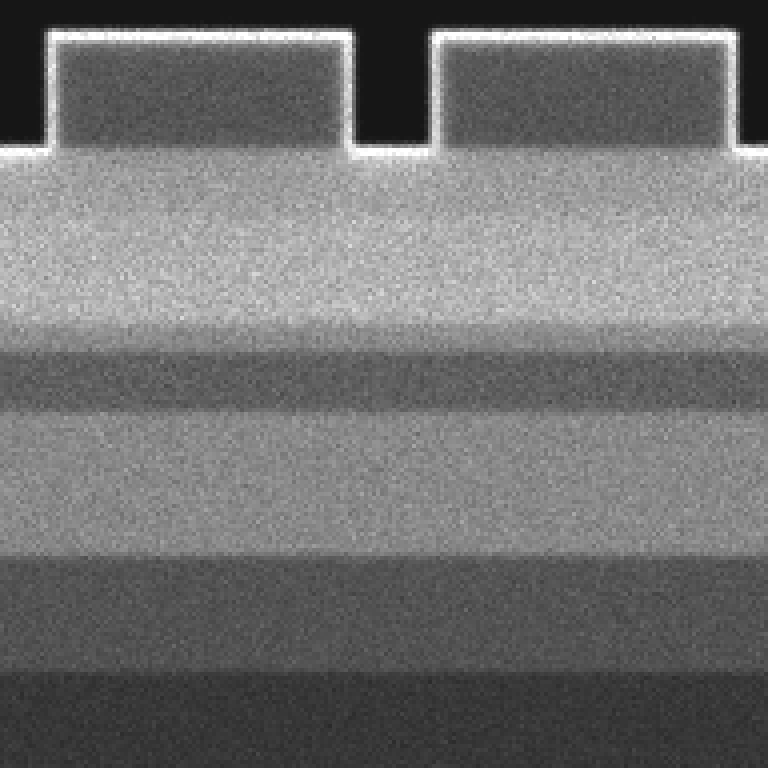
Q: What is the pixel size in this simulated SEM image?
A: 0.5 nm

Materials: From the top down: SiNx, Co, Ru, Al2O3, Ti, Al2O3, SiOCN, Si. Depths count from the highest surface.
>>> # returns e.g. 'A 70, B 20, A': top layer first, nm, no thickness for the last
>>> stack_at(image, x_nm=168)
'SiNx 58, Co 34, Ru 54, Al2O3 14, Ti 30, Al2O3 72, SiOCN 58, Si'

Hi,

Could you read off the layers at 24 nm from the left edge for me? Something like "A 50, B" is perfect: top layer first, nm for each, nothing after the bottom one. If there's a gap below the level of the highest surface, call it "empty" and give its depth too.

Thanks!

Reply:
SiNx 58, Co 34, Ru 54, Al2O3 14, Ti 30, Al2O3 72, SiOCN 58, Si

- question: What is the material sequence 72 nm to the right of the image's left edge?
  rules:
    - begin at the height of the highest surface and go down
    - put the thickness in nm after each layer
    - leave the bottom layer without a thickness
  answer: SiNx 58, Co 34, Ru 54, Al2O3 14, Ti 30, Al2O3 72, SiOCN 58, Si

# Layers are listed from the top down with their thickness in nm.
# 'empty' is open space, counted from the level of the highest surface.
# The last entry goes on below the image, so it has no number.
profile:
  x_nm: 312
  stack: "SiNx 58, Co 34, Ru 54, Al2O3 14, Ti 30, Al2O3 72, SiOCN 58, Si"